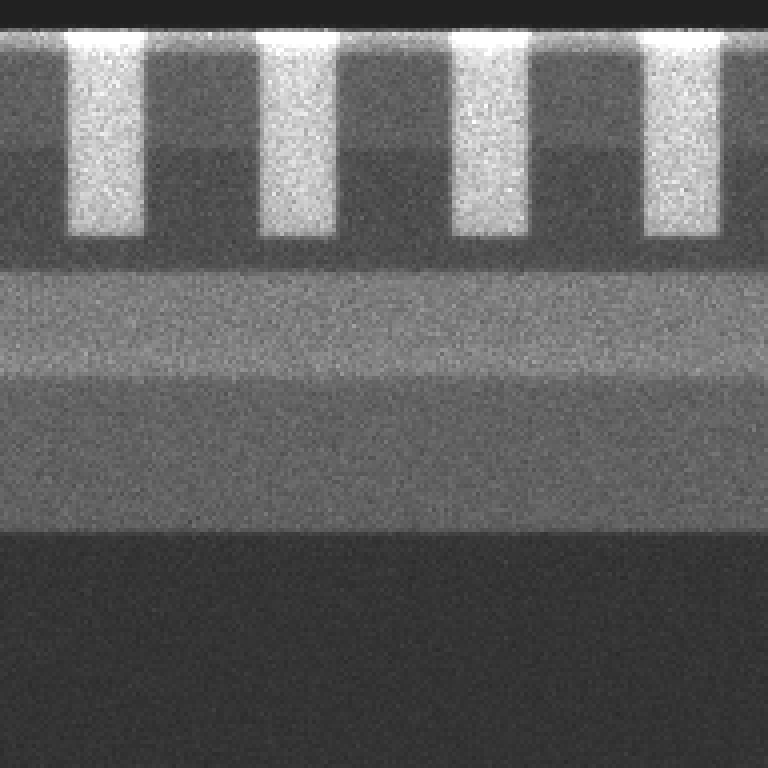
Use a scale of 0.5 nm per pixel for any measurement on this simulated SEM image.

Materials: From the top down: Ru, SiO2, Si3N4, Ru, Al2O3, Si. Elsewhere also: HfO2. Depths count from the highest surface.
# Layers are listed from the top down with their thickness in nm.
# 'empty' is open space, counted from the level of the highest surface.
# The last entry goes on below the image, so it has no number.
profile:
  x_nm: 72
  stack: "Ru 10, SiO2 48, Si3N4 62, Ru 52, Al2O3 78, Si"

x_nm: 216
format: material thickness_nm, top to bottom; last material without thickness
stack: Ru 10, SiO2 48, Si3N4 62, Ru 52, Al2O3 78, Si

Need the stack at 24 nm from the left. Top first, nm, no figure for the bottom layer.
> Ru 10, SiO2 48, Si3N4 62, Ru 52, Al2O3 78, Si